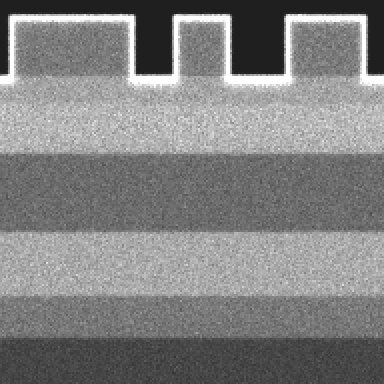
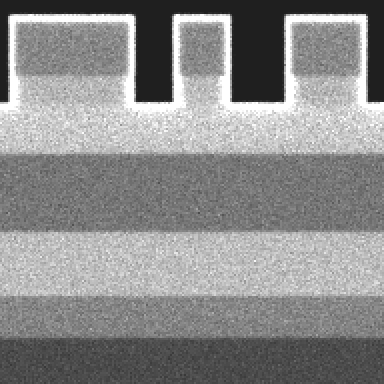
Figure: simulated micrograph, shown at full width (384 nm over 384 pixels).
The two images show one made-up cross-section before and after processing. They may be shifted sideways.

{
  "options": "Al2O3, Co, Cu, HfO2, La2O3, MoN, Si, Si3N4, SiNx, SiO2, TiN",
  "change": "removed",
  "material": "SiO2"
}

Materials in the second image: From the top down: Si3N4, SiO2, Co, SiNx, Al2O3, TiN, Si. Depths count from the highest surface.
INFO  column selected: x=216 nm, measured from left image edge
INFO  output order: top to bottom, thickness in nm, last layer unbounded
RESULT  Si3N4 60, SiO2 28, Co 50, SiNx 78, Al2O3 64, TiN 42, Si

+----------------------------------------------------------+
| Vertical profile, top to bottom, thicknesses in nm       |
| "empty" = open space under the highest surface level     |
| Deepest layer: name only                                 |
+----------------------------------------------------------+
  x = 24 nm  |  Si3N4 60, SiO2 28, Co 50, SiNx 78, Al2O3 64, TiN 42, Si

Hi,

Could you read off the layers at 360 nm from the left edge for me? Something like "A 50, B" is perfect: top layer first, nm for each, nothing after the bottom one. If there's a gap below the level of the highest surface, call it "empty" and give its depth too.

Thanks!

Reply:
Si3N4 60, SiO2 28, Co 50, SiNx 78, Al2O3 64, TiN 42, Si